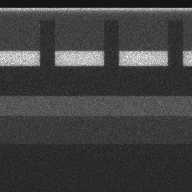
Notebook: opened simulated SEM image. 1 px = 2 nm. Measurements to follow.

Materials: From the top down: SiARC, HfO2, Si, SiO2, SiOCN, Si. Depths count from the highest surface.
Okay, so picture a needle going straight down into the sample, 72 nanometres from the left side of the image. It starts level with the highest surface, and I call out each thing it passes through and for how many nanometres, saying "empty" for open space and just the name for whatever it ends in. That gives SiARC 86, HfO2 30, Si 60, SiO2 40, SiOCN 56, Si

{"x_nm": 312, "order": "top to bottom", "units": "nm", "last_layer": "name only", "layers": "SiARC 86, HfO2 30, Si 60, SiO2 40, SiOCN 56, Si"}